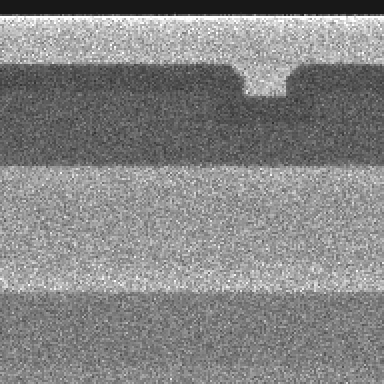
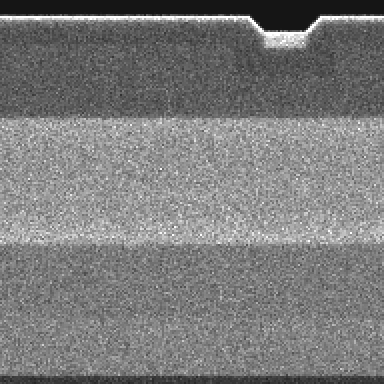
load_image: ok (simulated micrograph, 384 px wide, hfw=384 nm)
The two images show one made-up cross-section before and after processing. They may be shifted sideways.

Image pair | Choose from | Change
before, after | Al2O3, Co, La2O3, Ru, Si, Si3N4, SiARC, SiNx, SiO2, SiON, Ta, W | W (removed)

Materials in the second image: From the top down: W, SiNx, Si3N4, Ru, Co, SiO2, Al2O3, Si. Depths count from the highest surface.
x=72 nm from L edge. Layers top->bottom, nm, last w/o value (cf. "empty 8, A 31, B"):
SiNx 28, Si3N4 74, Ru 84, Co 42, SiO2 74, Al2O3 58, Si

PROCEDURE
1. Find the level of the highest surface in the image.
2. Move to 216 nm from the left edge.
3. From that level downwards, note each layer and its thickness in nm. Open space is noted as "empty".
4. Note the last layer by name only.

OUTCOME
SiNx 28, Si3N4 74, Ru 84, Co 42, SiO2 74, Al2O3 58, Si